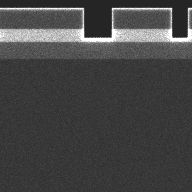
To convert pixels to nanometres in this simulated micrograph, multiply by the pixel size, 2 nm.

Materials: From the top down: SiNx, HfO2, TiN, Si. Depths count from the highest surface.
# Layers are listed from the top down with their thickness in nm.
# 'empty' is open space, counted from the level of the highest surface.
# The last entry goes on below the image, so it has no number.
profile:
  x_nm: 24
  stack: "SiNx 42, HfO2 26, TiN 34, Si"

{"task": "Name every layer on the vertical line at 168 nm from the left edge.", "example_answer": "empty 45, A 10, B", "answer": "empty 60, HfO2 8, TiN 34, Si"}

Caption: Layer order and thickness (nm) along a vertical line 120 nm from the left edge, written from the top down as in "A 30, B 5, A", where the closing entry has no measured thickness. SiNx 42, HfO2 26, TiN 34, Si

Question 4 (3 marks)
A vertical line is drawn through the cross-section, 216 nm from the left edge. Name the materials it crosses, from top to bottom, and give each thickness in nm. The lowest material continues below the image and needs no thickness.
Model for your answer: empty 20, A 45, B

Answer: empty 60, HfO2 8, TiN 34, Si